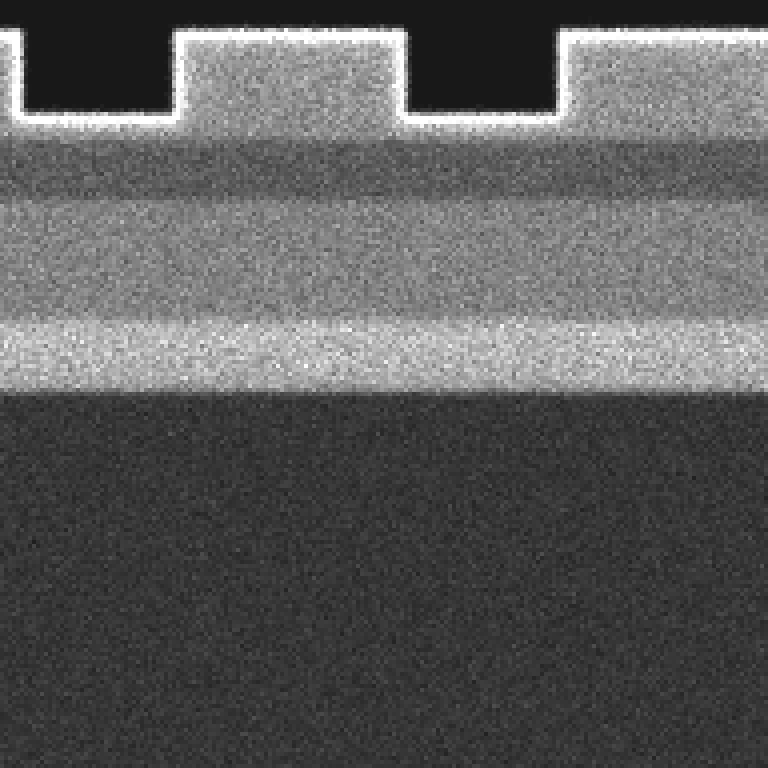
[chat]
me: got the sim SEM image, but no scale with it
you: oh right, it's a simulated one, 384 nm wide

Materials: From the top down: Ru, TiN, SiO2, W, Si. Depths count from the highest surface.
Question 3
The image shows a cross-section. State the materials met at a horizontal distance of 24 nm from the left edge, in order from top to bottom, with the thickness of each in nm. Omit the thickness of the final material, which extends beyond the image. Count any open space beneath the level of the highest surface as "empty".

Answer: empty 42, Ru 12, TiN 30, SiO2 60, W 36, Si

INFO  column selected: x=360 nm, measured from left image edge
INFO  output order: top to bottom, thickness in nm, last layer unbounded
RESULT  Ru 54, TiN 30, SiO2 60, W 36, Si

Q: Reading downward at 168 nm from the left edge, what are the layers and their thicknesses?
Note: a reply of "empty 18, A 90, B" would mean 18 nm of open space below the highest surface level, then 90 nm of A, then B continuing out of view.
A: Ru 54, TiN 30, SiO2 60, W 36, Si